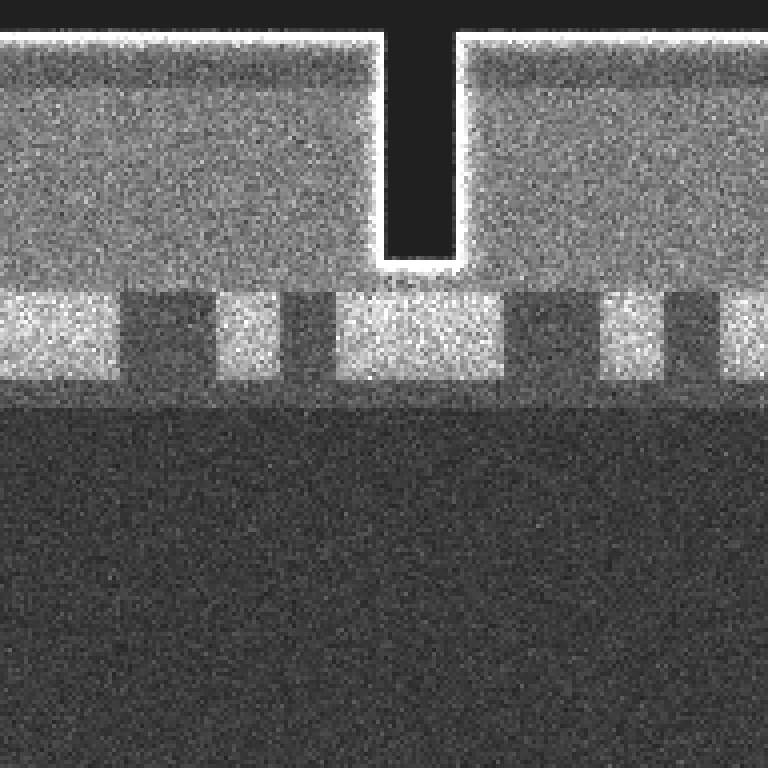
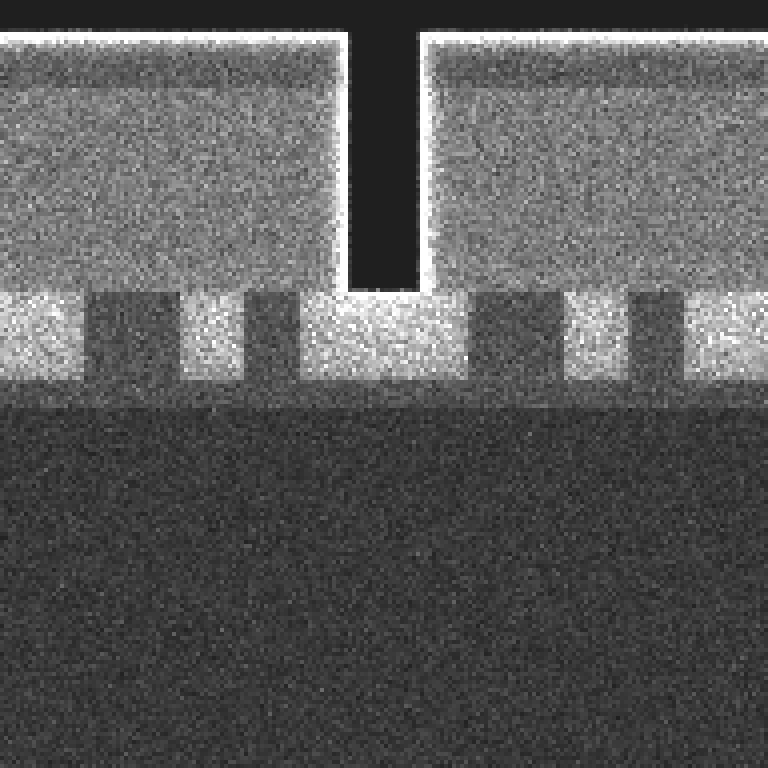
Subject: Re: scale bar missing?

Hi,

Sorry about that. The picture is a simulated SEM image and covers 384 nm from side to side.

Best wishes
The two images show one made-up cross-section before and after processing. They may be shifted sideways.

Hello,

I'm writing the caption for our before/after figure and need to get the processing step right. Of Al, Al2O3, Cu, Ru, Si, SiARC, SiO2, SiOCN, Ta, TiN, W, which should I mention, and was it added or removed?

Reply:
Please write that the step removed Al2O3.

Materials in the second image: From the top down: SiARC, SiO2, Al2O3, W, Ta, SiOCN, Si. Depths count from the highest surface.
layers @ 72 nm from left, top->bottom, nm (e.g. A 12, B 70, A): SiARC 28, SiO2 86, Al2O3 16, SiOCN 58, Si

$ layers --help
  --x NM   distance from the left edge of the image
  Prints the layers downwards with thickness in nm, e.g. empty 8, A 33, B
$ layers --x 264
SiARC 28, SiO2 86, Al2O3 16, SiOCN 58, Si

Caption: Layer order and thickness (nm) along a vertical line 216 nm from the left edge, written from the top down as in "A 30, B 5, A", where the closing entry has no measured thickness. SiARC 28, SiO2 86, Al2O3 16, W 36, Ta 8, SiOCN 14, Si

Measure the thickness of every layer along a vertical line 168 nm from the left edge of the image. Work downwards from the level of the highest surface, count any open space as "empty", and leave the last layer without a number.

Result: SiARC 28, SiO2 86, Al2O3 16, W 36, Ta 8, SiOCN 14, Si